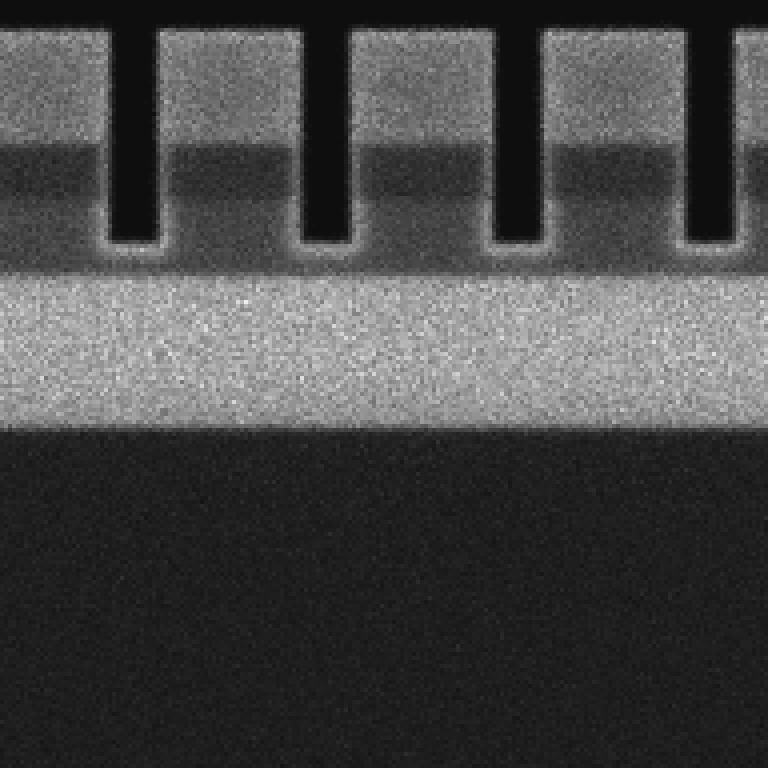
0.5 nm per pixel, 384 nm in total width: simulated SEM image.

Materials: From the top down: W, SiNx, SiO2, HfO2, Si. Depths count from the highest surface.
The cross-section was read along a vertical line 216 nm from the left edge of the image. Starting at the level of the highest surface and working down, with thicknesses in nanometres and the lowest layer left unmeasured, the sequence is W 56, SiNx 28, SiO2 38, HfO2 76, Si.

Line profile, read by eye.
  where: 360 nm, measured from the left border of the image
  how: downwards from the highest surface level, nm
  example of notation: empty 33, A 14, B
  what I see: empty 106, SiO2 16, HfO2 76, Si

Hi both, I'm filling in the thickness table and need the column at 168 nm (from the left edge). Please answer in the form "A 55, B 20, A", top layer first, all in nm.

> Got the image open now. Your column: empty 106, SiO2 16, HfO2 76, Si